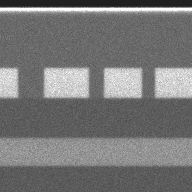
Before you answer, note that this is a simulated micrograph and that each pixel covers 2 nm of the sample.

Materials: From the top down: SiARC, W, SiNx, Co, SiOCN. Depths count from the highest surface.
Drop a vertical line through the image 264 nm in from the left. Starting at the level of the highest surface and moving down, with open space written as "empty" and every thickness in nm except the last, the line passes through SiARC 120, W 60, SiNx 80, Co 56, SiOCN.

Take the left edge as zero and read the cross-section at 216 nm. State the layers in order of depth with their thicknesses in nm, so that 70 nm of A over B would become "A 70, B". SiARC 120, W 60, SiNx 80, Co 56, SiOCN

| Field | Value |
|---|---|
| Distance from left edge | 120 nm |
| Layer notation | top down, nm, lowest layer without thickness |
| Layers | SiARC 120, W 60, SiNx 80, Co 56, SiOCN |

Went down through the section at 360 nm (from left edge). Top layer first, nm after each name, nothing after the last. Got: SiARC 120, W 60, SiNx 80, Co 56, SiOCN